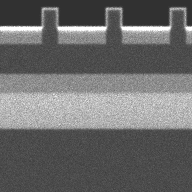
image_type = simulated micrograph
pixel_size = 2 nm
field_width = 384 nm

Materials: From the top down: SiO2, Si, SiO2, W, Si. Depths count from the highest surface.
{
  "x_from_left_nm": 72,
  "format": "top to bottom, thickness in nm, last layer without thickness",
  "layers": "empty 38, SiO2 34, Si 60, SiO2 38, W 72, Si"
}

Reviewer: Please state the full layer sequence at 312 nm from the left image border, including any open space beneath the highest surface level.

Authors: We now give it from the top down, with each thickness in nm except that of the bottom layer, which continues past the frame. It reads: empty 38, SiO2 34, Si 60, SiO2 38, W 72, Si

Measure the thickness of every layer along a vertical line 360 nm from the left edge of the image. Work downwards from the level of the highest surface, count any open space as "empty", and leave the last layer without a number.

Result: Si 132, SiO2 38, W 72, Si